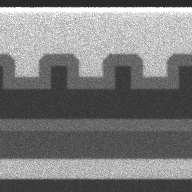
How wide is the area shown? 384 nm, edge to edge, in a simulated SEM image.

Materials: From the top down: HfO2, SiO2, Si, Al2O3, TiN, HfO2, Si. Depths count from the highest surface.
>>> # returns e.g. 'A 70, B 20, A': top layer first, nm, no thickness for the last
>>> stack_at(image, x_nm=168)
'HfO2 138, SiO2 24, Si 60, Al2O3 24, TiN 56, HfO2 40, Si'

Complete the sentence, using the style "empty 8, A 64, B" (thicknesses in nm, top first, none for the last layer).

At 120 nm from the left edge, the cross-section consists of HfO2 92, SiO2 24, Si 106, Al2O3 24, TiN 56, HfO2 40, Si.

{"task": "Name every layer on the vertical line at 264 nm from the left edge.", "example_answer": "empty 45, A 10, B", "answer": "HfO2 92, SiO2 70, Si 60, Al2O3 24, TiN 56, HfO2 40, Si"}